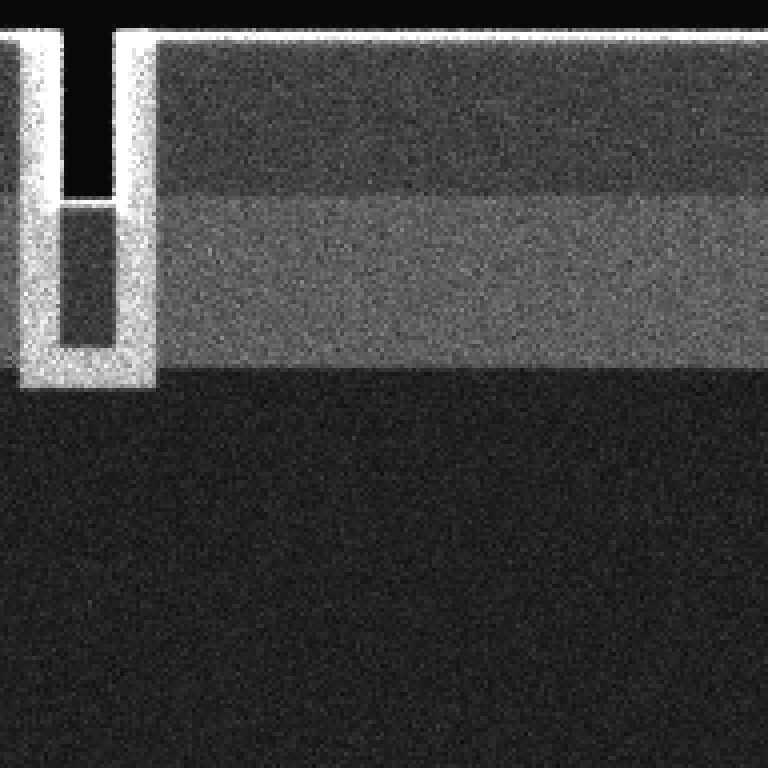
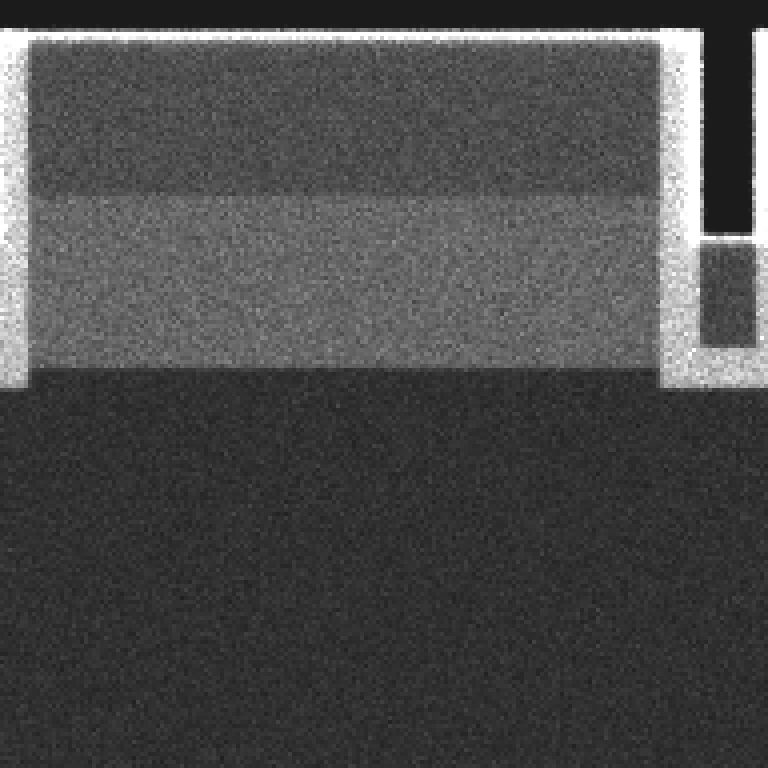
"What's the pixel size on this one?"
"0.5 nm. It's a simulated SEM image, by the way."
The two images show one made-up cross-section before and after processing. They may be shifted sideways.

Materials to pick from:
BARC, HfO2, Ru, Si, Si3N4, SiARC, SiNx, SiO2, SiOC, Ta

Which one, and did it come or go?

SiNx - removed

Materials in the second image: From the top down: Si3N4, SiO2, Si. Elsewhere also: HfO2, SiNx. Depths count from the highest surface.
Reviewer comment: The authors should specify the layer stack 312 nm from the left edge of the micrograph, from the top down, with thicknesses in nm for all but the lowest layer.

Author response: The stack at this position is Si3N4 82, SiO2 86, Si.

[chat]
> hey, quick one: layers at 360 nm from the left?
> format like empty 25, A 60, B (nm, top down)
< empty 102, SiNx 56, HfO2 20, Si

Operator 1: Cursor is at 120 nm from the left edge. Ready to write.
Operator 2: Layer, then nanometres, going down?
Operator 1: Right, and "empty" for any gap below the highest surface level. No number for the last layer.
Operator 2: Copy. Si3N4 82, SiO2 86, Si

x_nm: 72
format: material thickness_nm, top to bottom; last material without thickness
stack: Si3N4 82, SiO2 86, Si